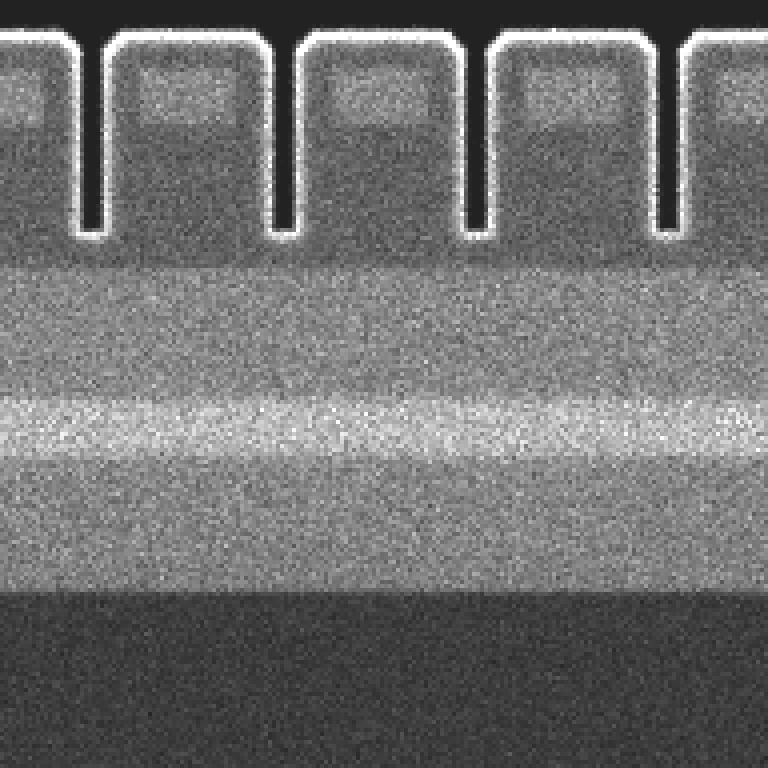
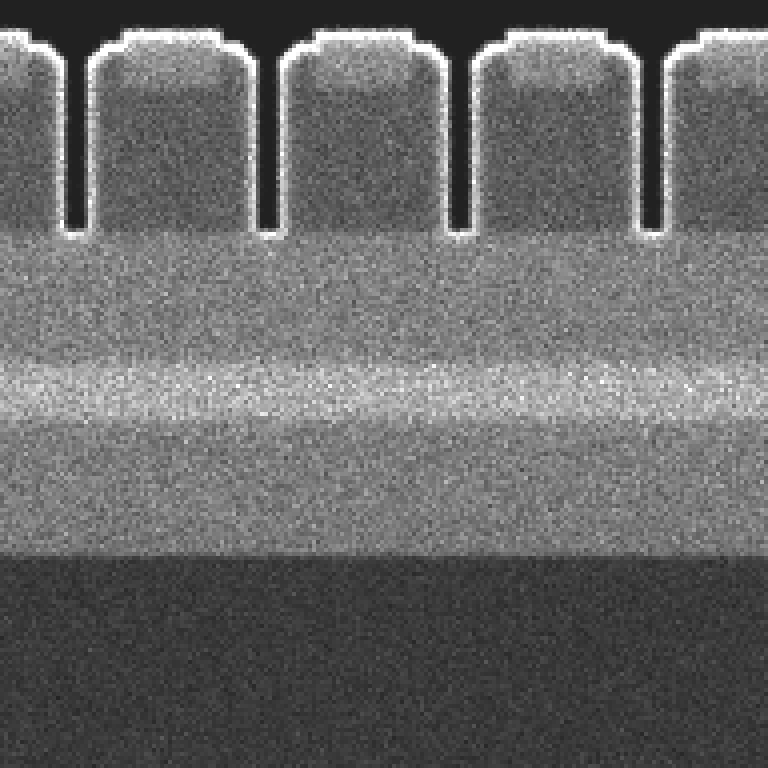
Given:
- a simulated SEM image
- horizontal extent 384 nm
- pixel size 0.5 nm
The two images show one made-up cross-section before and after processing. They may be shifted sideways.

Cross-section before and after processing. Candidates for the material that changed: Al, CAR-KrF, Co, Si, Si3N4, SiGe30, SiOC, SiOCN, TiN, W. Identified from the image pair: Si3N4 (removed).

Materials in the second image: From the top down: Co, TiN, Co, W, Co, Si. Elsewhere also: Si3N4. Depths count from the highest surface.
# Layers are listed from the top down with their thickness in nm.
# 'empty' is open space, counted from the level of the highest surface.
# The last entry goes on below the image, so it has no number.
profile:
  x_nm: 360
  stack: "Co 28, TiN 72, Co 66, W 28, Co 68, Si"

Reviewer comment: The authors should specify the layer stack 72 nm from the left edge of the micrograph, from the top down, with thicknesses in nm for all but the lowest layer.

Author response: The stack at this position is Co 28, TiN 72, Co 66, W 28, Co 68, Si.